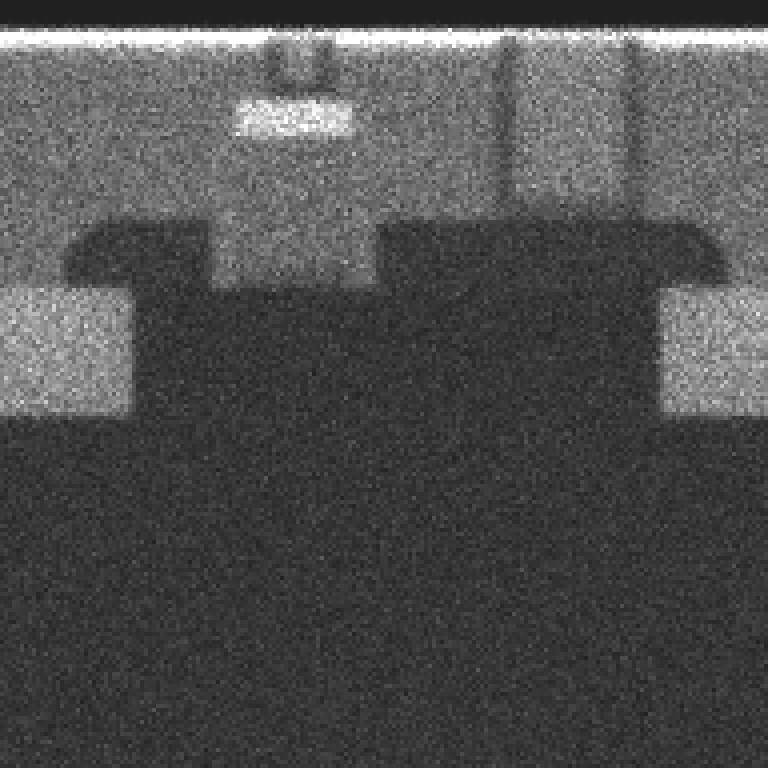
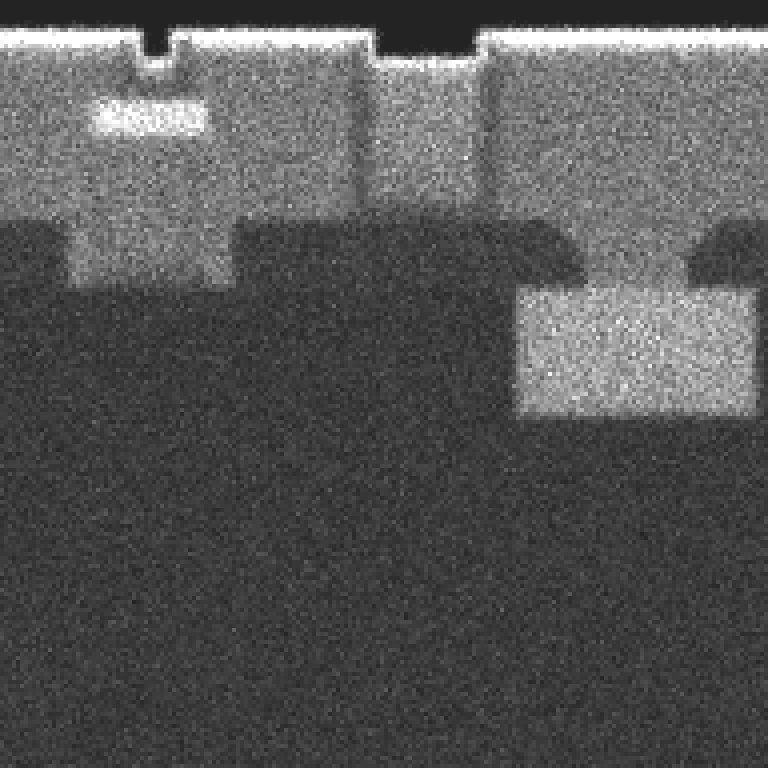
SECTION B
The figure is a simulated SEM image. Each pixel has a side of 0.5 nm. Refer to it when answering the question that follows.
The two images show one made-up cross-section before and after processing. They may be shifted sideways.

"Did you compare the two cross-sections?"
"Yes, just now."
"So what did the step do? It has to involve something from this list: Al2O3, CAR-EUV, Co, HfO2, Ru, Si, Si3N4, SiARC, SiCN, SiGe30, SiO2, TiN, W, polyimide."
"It removed Ru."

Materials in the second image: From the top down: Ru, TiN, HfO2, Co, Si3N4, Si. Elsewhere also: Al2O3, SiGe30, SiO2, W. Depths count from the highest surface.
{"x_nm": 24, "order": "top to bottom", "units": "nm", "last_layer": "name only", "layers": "SiO2 94, SiGe30 34, Si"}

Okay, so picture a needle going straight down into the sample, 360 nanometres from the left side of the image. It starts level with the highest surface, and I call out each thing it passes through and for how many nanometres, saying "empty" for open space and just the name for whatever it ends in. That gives SiO2 94, SiGe30 34, W 64, Si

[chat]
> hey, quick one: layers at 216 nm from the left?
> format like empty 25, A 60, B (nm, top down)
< empty 14, Ru 70, TiN 10, SiGe30 34, Si